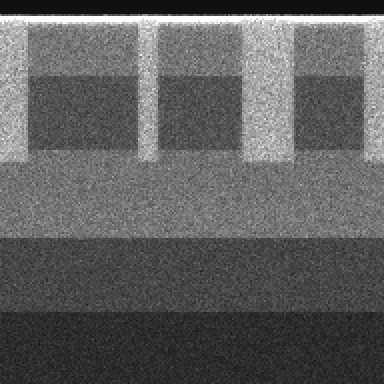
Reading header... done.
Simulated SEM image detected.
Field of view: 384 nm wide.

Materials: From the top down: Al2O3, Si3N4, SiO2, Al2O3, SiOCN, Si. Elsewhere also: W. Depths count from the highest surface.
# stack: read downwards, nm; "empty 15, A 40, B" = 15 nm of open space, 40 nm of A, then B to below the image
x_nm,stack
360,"Al2O3 60, Si3N4 74, SiO2 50, Al2O3 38, SiOCN 74, Si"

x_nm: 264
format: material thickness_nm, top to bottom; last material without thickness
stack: W 146, SiO2 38, Al2O3 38, SiOCN 74, Si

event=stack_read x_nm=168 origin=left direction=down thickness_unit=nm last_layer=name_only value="Al2O3 60, Si3N4 74, SiO2 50, Al2O3 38, SiOCN 74, Si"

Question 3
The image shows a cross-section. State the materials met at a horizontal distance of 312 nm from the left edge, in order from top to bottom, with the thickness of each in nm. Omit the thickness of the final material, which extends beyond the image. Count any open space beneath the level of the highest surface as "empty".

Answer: Al2O3 60, Si3N4 74, SiO2 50, Al2O3 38, SiOCN 74, Si